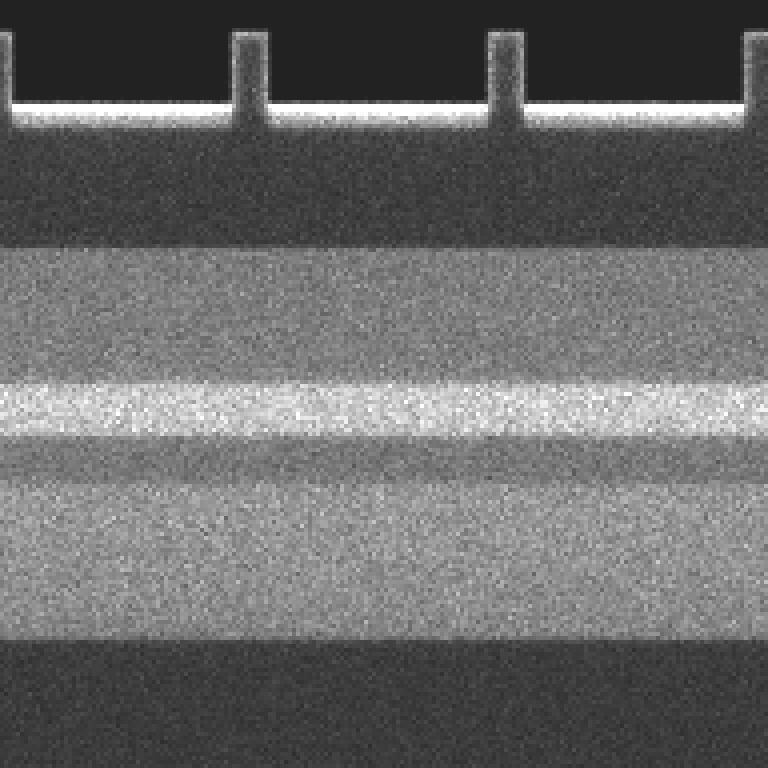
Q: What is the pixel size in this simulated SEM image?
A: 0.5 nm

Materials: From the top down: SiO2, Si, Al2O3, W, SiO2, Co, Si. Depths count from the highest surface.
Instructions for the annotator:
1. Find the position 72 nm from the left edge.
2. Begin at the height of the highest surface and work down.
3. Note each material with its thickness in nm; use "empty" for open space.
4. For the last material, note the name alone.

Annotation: empty 36, SiO2 12, Si 60, Al2O3 68, W 26, SiO2 24, Co 78, Si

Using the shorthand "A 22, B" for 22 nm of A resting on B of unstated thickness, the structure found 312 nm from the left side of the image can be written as empty 36, SiO2 12, Si 60, Al2O3 68, W 26, SiO2 24, Co 78, Si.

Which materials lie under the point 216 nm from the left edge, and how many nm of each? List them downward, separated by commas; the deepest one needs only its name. empty 36, SiO2 12, Si 60, Al2O3 68, W 26, SiO2 24, Co 78, Si